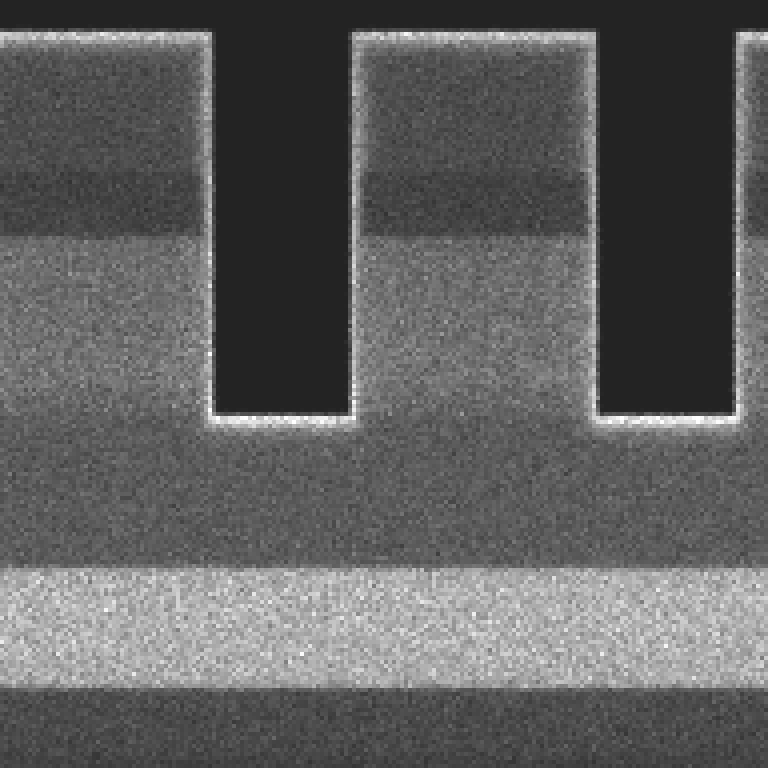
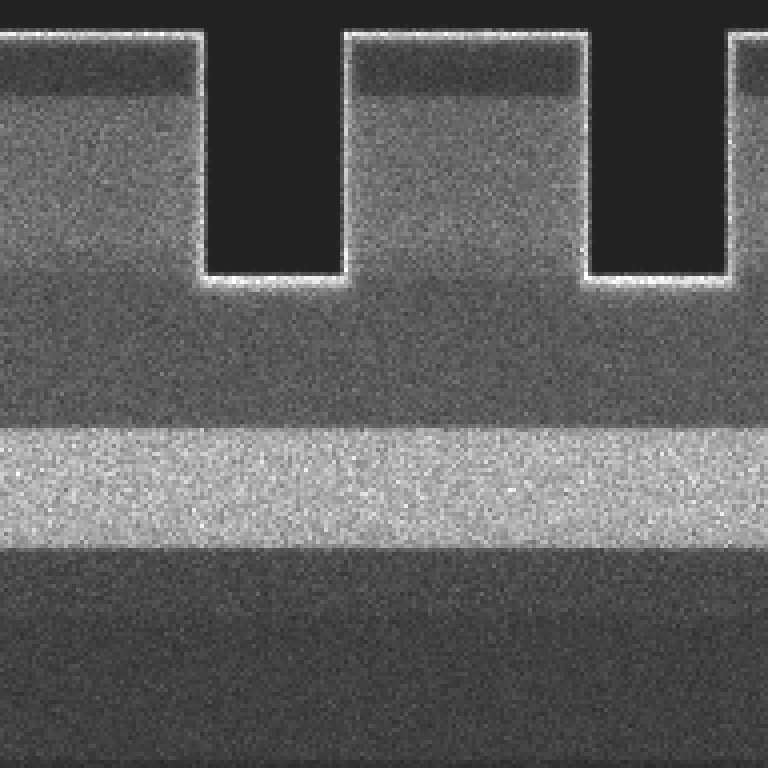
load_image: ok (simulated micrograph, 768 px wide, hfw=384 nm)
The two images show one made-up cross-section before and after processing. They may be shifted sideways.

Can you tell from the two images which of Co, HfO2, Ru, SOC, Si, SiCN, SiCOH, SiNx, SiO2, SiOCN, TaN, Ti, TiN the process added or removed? Yes, it removed SOC.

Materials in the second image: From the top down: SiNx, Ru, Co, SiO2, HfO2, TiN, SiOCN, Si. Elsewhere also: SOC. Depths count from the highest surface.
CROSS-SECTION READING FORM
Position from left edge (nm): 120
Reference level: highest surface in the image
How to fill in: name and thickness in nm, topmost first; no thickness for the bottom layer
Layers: empty 122, SiO2 76, HfO2 60, TiN 34, SiOCN 72, Si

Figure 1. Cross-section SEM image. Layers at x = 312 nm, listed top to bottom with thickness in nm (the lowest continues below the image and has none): empty 122, SiO2 76, HfO2 60, TiN 34, SiOCN 72, Si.